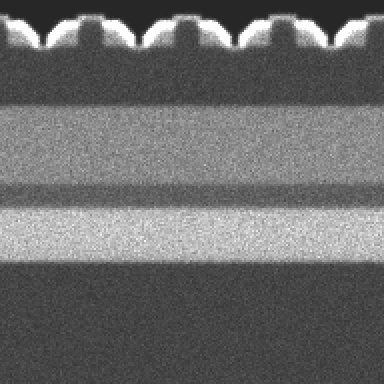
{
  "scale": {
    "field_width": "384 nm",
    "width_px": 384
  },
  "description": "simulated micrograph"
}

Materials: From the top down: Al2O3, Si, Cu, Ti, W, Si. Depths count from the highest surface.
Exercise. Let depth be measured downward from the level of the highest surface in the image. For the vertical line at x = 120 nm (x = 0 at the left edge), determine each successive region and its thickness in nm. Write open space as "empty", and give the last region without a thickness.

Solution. empty 8, Al2O3 22, Si 60, Cu 78, Ti 24, W 54, Si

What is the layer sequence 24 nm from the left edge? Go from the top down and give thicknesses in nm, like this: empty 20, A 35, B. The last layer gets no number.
empty 8, Al2O3 22, Si 60, Cu 78, Ti 24, W 54, Si